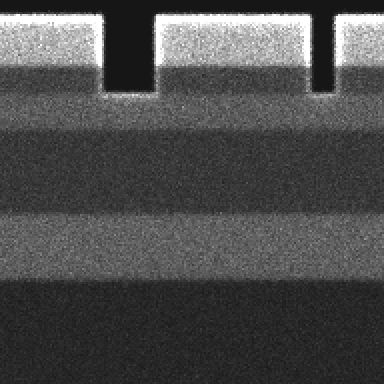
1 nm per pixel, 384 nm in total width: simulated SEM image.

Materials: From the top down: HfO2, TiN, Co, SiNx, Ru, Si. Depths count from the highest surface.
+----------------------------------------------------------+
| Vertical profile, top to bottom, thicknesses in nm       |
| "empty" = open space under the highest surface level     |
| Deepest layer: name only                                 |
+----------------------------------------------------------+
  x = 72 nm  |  HfO2 50, TiN 28, Co 36, SiNx 84, Ru 66, Si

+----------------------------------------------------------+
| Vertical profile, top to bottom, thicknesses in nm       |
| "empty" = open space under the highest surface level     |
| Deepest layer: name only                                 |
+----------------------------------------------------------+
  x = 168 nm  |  HfO2 50, TiN 28, Co 36, SiNx 84, Ru 66, Si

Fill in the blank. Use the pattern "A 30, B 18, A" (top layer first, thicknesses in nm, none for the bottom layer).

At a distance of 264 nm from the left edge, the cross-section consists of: HfO2 50, TiN 28, Co 36, SiNx 84, Ru 66, Si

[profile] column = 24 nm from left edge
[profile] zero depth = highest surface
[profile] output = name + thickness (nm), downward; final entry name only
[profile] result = HfO2 50, TiN 28, Co 36, SiNx 84, Ru 66, Si